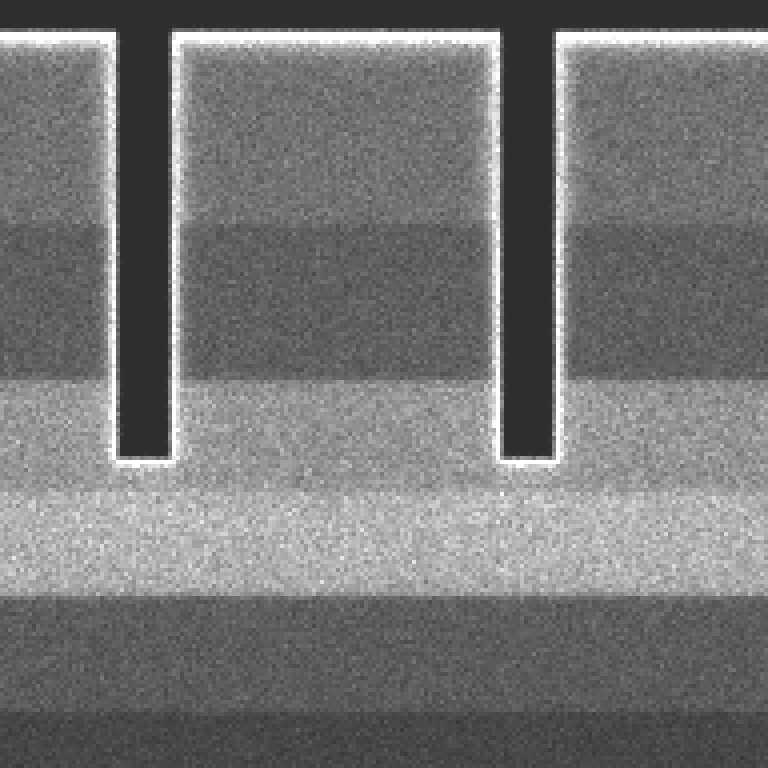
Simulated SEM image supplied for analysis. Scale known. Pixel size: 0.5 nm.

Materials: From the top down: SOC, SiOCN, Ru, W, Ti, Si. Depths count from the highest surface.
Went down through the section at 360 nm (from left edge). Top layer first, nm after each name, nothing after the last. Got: SOC 96, SiOCN 78, Ru 56, W 52, Ti 58, Si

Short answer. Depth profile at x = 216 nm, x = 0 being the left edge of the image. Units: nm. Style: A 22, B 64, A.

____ SOC 96, SiOCN 78, Ru 56, W 52, Ti 58, Si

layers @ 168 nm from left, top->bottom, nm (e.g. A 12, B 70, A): SOC 96, SiOCN 78, Ru 56, W 52, Ti 58, Si